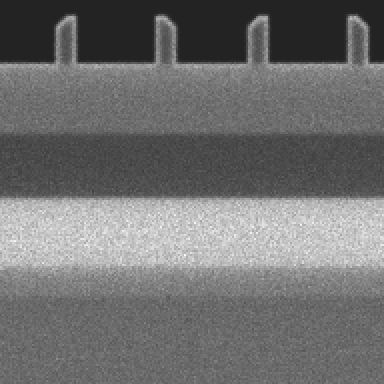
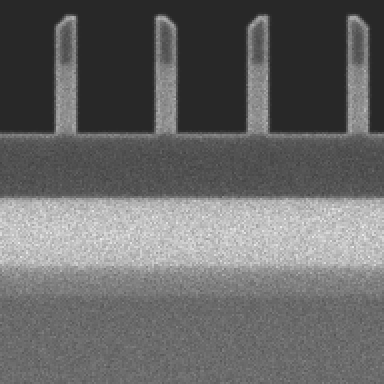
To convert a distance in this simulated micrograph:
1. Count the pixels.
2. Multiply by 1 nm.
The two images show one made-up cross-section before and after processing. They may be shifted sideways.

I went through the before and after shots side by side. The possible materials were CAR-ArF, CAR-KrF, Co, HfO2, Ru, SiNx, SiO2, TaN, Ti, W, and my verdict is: removed, Ru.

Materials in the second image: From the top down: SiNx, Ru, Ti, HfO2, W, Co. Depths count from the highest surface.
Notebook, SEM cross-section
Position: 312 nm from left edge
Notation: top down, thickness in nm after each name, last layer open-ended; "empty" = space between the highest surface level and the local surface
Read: empty 118, Ti 64, HfO2 68, W 30, Co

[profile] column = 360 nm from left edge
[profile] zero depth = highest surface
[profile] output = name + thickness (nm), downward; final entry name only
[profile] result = empty 4, SiNx 44, Ru 70, Ti 64, HfO2 68, W 30, Co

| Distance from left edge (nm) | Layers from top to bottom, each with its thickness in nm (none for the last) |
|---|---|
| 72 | SiNx 48, Ru 70, Ti 64, HfO2 68, W 30, Co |